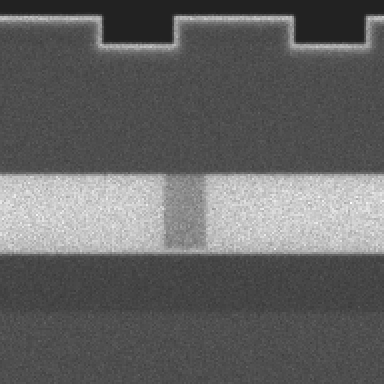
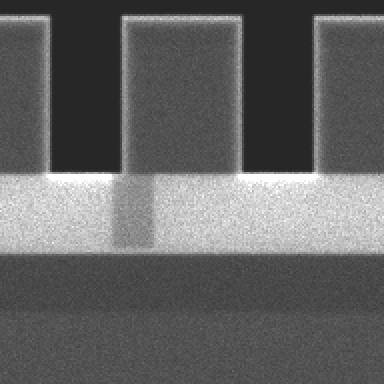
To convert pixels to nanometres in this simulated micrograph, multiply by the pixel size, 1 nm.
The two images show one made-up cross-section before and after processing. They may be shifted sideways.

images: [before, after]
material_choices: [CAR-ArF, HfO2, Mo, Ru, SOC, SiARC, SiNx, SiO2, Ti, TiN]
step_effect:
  removed: SOC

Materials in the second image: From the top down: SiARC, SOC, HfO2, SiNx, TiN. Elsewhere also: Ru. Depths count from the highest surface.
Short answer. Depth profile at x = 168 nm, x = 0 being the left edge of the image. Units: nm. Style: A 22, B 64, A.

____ SiARC 28, SOC 130, HfO2 80, SiNx 58, TiN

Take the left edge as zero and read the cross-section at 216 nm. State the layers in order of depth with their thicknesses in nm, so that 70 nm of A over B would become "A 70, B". SiARC 28, SOC 130, HfO2 80, SiNx 58, TiN